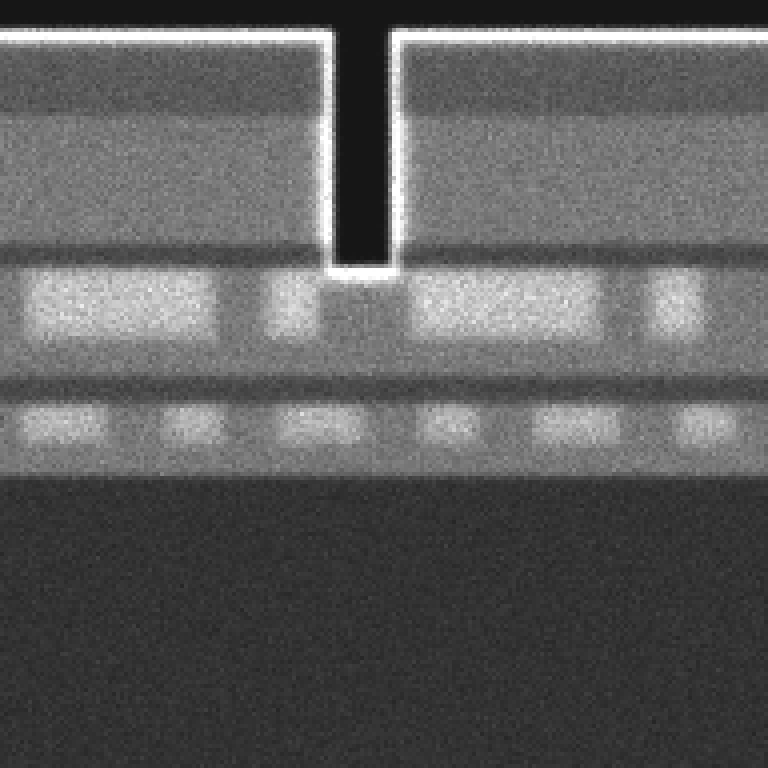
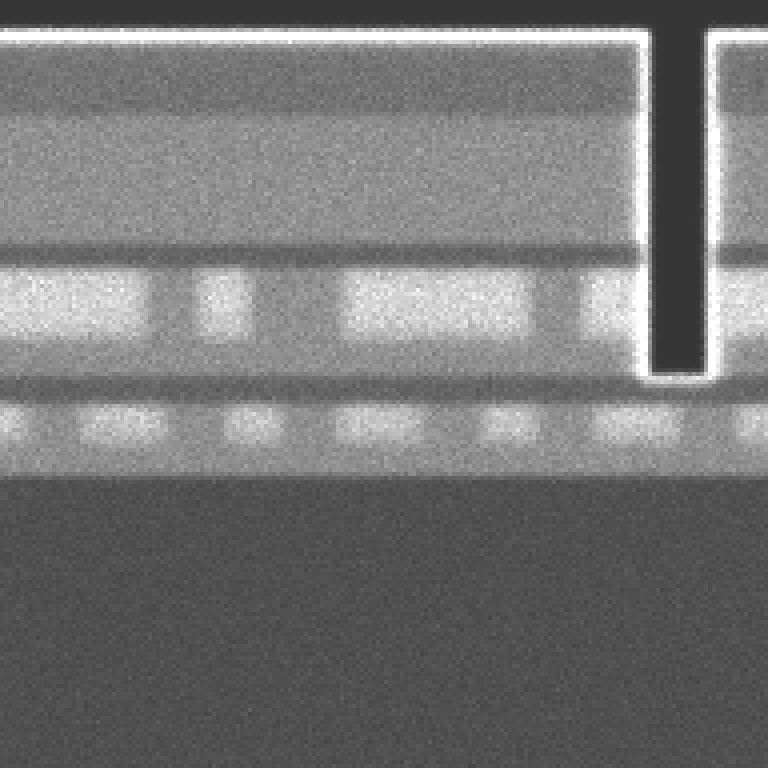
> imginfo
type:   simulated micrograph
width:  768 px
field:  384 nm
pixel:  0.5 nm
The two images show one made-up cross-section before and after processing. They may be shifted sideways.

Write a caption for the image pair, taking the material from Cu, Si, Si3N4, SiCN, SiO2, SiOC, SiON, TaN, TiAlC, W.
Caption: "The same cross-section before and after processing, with SiO2 removed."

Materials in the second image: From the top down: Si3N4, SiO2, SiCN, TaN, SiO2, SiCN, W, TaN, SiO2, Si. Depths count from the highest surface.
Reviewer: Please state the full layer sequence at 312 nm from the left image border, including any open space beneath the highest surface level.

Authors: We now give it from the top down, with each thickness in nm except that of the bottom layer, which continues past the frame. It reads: Si3N4 42, SiO2 64, SiCN 12, TaN 36, SiO2 18, SiCN 14, W 14, TaN 6, SiO2 16, Si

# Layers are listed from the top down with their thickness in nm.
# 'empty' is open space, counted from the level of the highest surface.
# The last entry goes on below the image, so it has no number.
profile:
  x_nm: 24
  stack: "Si3N4 42, SiO2 64, SiCN 12, W 30, TaN 6, SiO2 18, SiCN 14, SiO2 36, Si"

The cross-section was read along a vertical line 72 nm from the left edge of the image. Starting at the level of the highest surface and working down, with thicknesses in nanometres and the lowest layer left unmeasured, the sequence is Si3N4 42, SiO2 64, SiCN 12, TaN 36, SiO2 18, SiCN 14, W 14, TaN 6, SiO2 16, Si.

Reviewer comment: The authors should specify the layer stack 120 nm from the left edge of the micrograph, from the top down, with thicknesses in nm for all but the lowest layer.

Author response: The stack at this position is Si3N4 42, SiO2 64, SiCN 12, TaN 36, SiO2 18, SiCN 14, W 14, TaN 6, SiO2 16, Si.